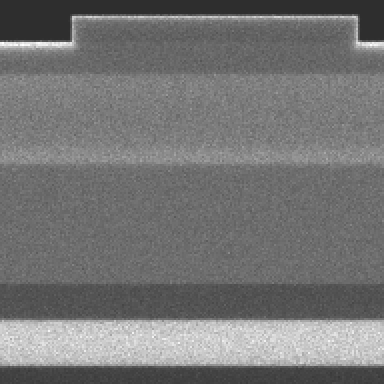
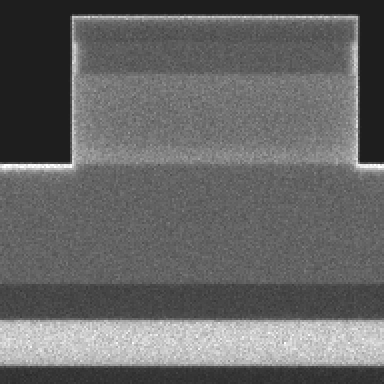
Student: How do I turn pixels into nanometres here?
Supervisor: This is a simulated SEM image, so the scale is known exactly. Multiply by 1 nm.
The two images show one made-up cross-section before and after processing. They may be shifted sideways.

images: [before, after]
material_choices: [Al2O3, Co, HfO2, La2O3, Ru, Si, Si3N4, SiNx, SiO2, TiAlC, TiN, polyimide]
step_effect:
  removed: Co and Ru and SiO2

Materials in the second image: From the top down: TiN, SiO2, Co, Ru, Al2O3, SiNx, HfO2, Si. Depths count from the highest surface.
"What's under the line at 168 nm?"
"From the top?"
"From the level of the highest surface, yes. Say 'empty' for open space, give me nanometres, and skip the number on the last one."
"TiN 26, SiO2 32, Co 74, Ru 16, Al2O3 120, SiNx 36, HfO2 46, Si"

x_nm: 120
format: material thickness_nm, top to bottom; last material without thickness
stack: TiN 26, SiO2 32, Co 74, Ru 16, Al2O3 120, SiNx 36, HfO2 46, Si